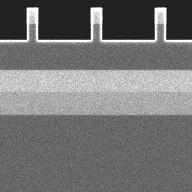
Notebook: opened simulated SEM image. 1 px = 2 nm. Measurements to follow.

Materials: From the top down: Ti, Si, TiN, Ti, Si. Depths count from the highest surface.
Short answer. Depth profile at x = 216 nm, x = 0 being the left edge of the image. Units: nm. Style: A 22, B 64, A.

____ empty 64, Si 60, TiN 44, Ti 46, Si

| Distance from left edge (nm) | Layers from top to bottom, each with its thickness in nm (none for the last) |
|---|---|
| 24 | empty 64, Si 60, TiN 44, Ti 46, Si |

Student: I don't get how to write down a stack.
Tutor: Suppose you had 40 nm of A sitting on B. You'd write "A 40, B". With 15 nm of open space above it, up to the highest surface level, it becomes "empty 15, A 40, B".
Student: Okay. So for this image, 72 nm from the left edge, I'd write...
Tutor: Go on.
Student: Ti 32, Si 92, TiN 44, Ti 46, Si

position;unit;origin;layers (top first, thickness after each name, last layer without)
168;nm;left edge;empty 64, Si 60, TiN 44, Ti 46, Si